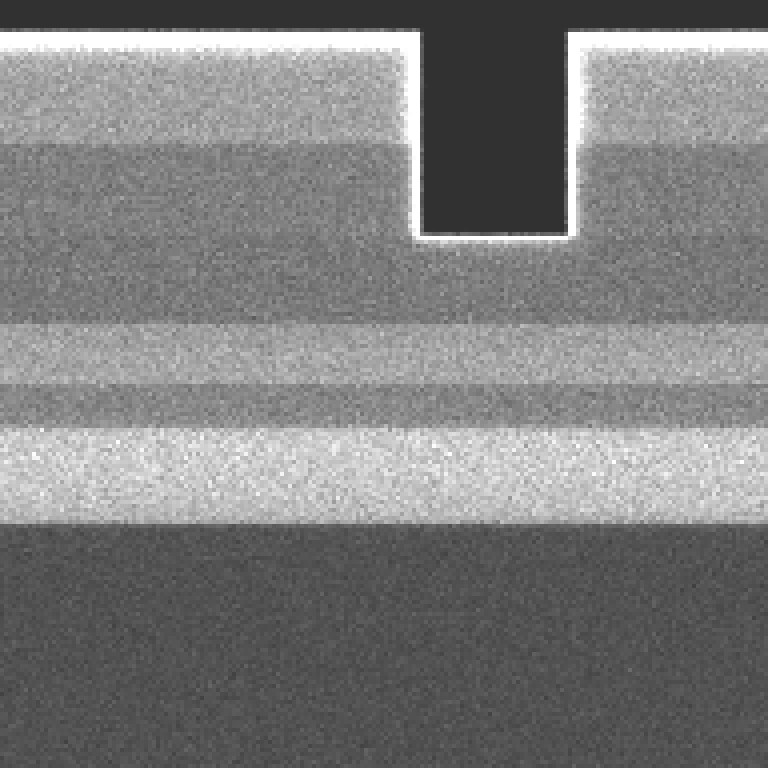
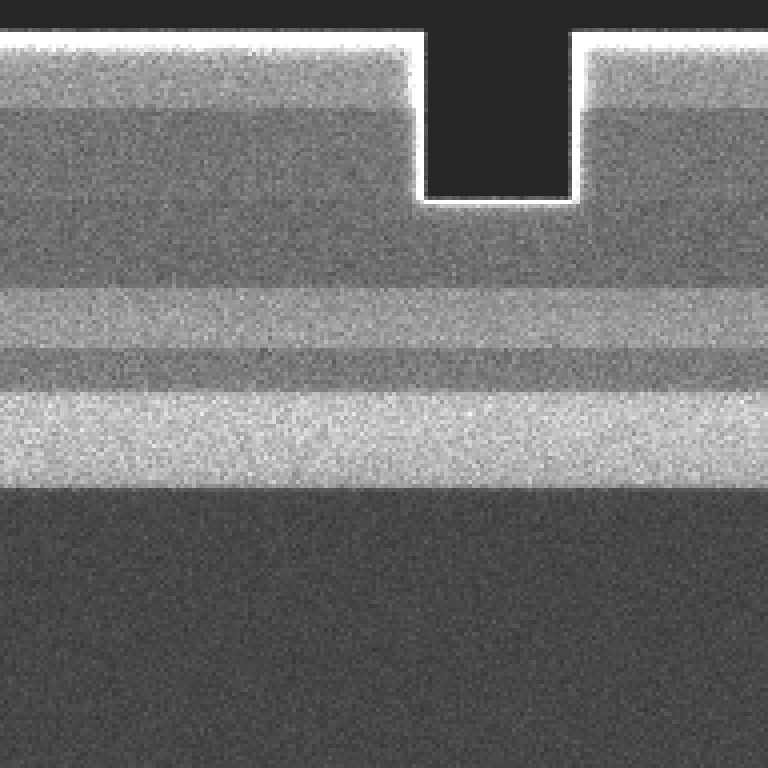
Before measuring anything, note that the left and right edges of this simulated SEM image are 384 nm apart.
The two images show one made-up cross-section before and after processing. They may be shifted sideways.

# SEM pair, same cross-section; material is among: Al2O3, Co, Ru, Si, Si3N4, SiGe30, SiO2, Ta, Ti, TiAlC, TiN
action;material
removed;SiO2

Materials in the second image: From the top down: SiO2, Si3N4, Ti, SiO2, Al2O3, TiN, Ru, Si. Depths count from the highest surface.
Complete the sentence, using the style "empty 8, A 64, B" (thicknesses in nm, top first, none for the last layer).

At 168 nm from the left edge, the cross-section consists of SiO2 38, Si3N4 46, Ti 44, SiO2 12, Al2O3 18, TiN 22, Ru 48, Si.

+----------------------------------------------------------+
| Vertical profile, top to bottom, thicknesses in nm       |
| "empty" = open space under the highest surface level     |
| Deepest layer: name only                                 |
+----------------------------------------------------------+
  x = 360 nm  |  SiO2 38, Si3N4 46, Ti 44, SiO2 12, Al2O3 18, TiN 22, Ru 48, Si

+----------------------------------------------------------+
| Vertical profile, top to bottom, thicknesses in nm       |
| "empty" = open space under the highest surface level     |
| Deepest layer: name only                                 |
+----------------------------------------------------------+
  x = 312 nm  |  SiO2 38, Si3N4 46, Ti 44, SiO2 12, Al2O3 18, TiN 22, Ru 48, Si